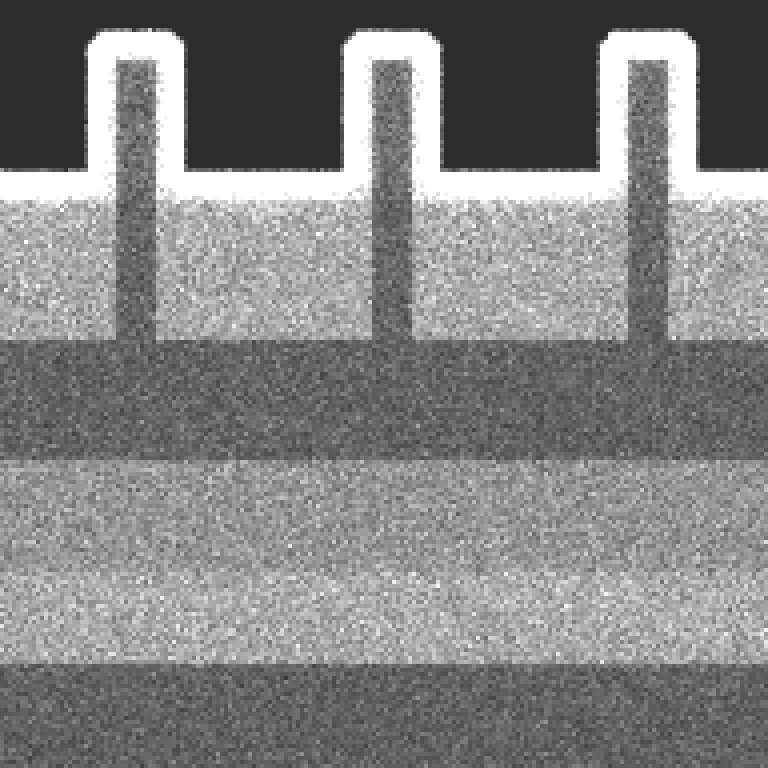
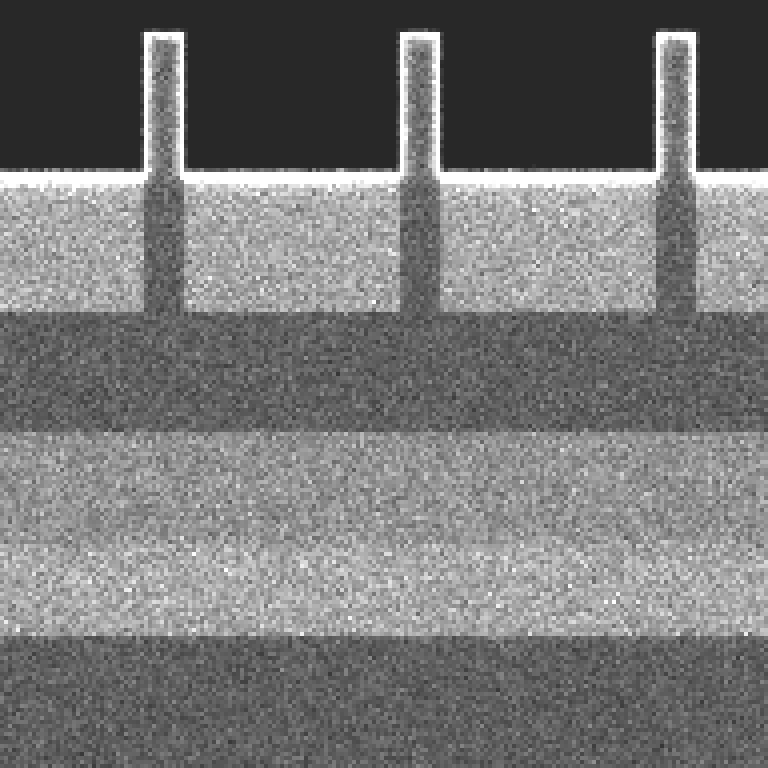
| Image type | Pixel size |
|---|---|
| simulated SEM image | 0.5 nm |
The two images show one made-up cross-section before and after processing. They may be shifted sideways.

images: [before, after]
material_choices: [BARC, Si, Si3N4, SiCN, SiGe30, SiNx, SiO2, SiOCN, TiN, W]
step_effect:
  removed: SiO2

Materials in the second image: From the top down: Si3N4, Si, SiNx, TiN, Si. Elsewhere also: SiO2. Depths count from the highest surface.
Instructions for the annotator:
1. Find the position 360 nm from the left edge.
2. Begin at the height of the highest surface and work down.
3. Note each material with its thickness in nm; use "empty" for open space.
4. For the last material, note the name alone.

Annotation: empty 70, Si3N4 70, Si 60, SiNx 56, TiN 46, Si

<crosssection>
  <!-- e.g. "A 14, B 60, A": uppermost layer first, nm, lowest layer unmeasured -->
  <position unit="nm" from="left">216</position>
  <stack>Si 200, SiNx 56, TiN 46, Si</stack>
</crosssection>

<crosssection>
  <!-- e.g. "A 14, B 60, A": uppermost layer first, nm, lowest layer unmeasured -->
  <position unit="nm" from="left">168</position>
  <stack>empty 70, Si3N4 70, Si 60, SiNx 56, TiN 46, Si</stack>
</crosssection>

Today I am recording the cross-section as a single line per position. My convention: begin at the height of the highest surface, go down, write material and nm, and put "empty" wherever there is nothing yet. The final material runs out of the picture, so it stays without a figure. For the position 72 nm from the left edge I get Si 200, SiNx 56, TiN 46, Si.